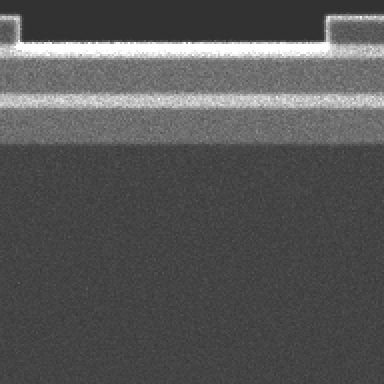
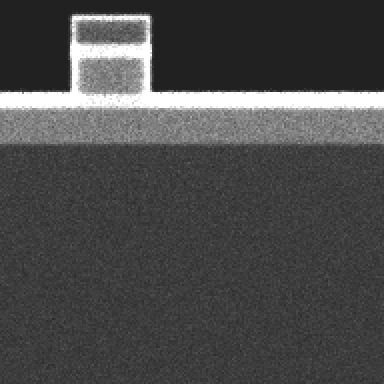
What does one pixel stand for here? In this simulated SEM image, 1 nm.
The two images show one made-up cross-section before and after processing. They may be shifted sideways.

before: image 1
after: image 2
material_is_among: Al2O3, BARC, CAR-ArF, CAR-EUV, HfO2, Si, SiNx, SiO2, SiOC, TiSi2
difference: HfO2 and SiO2, removed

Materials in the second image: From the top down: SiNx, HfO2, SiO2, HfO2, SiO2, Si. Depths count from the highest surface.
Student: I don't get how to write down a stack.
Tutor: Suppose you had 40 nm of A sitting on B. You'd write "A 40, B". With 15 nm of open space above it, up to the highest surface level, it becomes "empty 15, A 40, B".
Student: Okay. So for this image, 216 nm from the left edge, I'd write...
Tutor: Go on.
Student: empty 78, HfO2 14, SiO2 36, Si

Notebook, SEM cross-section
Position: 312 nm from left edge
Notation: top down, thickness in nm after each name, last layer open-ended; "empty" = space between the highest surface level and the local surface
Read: empty 78, HfO2 14, SiO2 36, Si